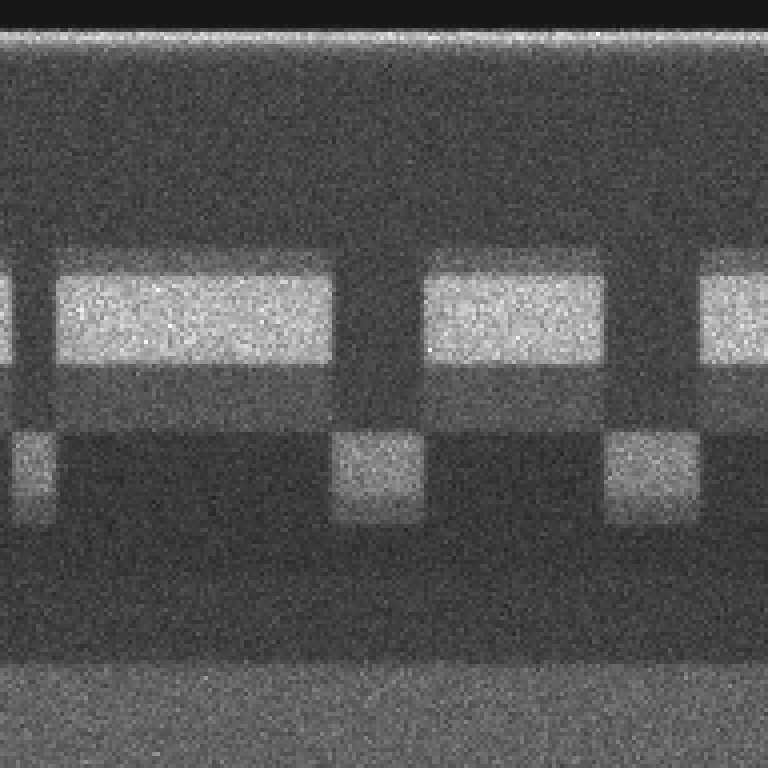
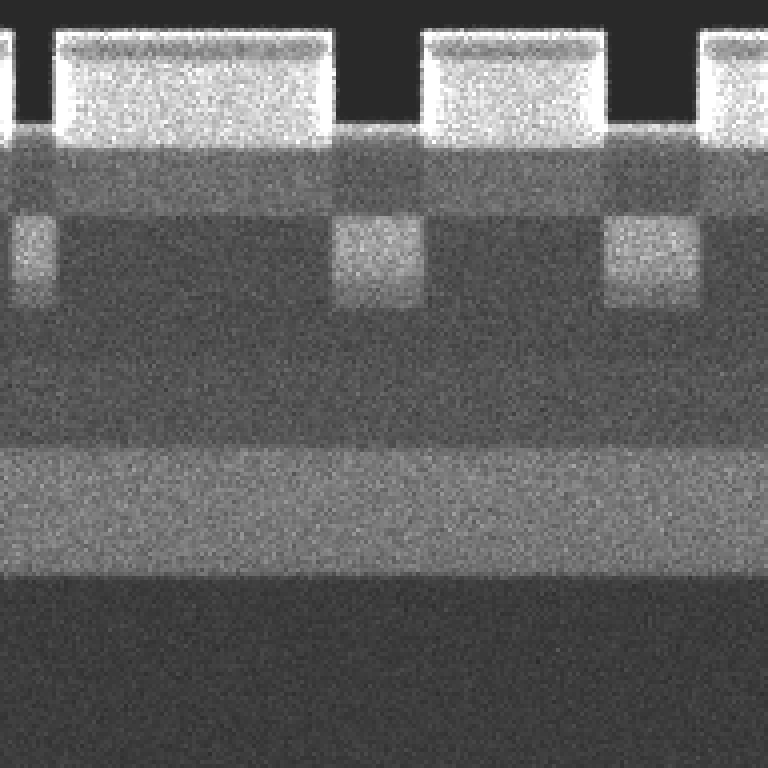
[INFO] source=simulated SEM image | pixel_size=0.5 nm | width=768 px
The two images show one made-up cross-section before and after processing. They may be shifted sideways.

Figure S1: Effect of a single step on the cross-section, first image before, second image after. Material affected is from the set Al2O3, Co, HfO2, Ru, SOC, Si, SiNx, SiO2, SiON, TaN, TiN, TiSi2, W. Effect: removed SOC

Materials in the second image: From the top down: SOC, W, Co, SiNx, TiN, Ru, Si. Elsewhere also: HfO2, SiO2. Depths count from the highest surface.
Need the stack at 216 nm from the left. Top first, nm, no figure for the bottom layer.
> Co 14, HfO2 44, SiO2 34, SiNx 72, TiN 44, Ru 64, Si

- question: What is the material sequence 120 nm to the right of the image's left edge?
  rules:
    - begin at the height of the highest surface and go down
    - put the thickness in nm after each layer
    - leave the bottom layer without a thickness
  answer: Co 14, HfO2 44, SiO2 34, SiNx 72, TiN 44, Ru 64, Si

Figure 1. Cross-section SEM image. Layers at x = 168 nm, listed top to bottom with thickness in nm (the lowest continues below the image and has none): empty 46, SOC 46, W 32, Co 14, SiNx 26, TiN 44, Ru 64, Si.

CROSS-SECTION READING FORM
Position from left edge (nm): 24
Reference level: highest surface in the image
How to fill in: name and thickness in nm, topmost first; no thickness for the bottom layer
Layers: empty 46, SOC 46, W 32, Co 14, SiNx 26, TiN 44, Ru 64, Si